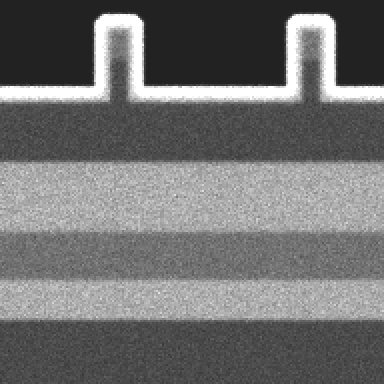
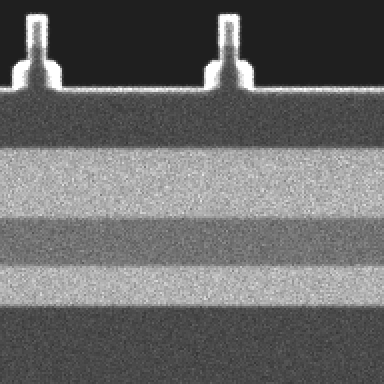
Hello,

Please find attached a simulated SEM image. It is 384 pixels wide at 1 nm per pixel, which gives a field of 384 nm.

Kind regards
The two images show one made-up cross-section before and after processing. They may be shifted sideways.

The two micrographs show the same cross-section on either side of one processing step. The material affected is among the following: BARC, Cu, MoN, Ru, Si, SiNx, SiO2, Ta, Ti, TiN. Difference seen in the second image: SiO2 removed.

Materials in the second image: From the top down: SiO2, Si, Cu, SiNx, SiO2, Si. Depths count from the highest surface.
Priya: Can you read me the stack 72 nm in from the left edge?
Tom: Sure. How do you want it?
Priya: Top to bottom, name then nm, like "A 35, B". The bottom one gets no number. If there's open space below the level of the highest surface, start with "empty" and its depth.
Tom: empty 72, Si 60, Cu 70, SiNx 48, SiO2 40, Si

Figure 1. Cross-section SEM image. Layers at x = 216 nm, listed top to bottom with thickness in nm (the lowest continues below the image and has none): empty 46, SiO2 26, Si 60, Cu 70, SiNx 48, SiO2 40, Si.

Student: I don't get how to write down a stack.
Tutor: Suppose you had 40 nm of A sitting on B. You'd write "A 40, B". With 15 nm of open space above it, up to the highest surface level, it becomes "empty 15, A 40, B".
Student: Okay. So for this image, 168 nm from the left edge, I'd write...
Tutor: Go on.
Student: empty 72, Si 60, Cu 70, SiNx 48, SiO2 40, Si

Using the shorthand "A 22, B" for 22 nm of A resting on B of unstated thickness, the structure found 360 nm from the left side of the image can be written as empty 72, Si 60, Cu 70, SiNx 48, SiO2 40, Si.